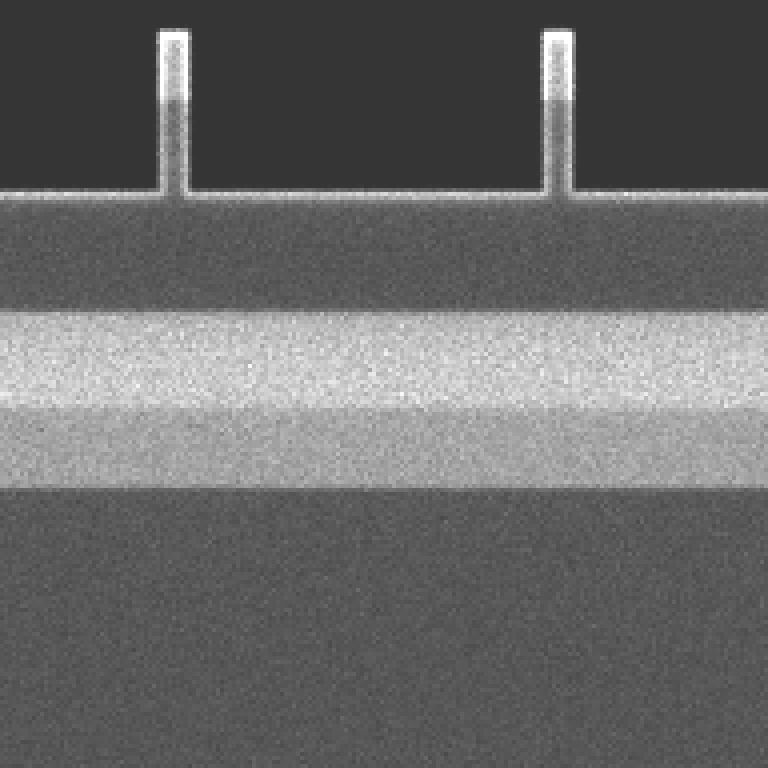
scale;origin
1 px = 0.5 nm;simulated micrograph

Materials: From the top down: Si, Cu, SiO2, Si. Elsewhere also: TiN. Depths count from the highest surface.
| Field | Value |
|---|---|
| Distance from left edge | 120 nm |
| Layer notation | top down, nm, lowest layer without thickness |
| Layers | empty 80, Si 60, Cu 48, SiO2 40, Si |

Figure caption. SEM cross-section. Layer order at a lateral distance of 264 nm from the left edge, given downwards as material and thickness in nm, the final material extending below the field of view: empty 80, Si 60, Cu 48, SiO2 40, Si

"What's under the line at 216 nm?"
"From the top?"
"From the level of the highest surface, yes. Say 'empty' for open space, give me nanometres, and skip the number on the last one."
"empty 80, Si 60, Cu 48, SiO2 40, Si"